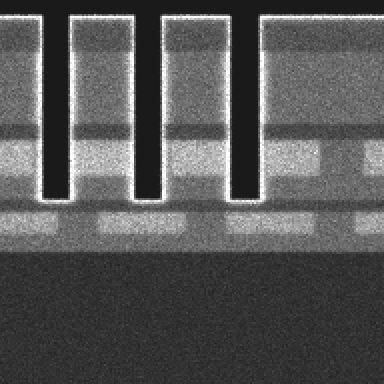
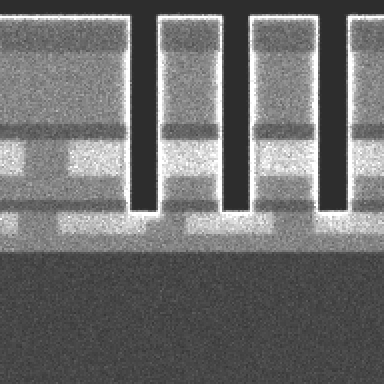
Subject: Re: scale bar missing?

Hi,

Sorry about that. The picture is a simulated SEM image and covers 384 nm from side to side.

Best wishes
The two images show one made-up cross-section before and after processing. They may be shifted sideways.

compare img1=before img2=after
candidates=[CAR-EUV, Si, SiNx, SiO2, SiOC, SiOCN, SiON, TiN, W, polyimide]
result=removed:SiNx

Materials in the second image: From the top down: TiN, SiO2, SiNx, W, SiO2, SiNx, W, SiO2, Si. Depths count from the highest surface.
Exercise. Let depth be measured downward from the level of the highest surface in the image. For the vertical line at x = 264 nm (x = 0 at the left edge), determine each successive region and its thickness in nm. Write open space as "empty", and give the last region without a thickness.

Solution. TiN 36, SiO2 72, SiNx 16, W 36, SiO2 24, SiNx 12, W 22, SiO2 18, Si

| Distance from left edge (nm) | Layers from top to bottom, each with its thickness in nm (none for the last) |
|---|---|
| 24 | TiN 36, SiO2 72, SiNx 16, SiO2 60, SiNx 12, SiO2 40, Si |